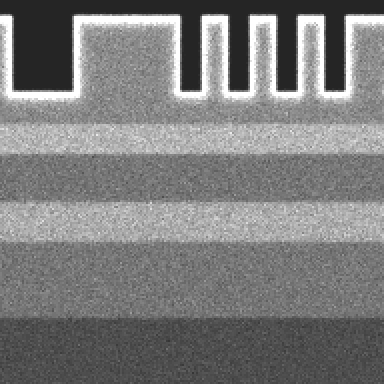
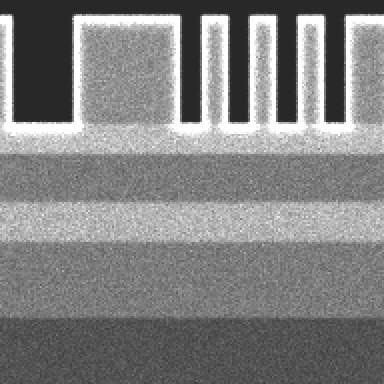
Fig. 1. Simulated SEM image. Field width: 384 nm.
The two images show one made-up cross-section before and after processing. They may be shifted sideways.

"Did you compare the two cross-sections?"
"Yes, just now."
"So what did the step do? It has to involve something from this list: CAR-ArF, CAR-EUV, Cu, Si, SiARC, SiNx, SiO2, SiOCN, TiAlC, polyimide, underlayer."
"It removed underlayer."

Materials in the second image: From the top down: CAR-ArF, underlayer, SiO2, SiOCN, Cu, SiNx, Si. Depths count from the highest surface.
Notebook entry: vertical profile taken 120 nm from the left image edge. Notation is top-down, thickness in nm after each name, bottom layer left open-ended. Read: CAR-ArF 76, underlayer 32, SiO2 30, SiOCN 48, Cu 40, SiNx 76, Si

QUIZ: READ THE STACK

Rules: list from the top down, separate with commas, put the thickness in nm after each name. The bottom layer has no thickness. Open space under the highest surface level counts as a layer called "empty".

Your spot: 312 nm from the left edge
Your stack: CAR-ArF 76, underlayer 32, SiO2 30, SiOCN 48, Cu 40, SiNx 76, Si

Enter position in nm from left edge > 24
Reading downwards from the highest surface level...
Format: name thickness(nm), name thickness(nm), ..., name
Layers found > empty 108, SiO2 30, SiOCN 48, Cu 40, SiNx 76, Si